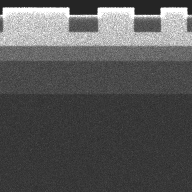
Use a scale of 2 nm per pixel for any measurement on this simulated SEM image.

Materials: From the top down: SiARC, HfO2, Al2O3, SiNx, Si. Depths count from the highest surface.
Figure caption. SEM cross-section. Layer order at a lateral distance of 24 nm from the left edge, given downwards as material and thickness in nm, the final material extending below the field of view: HfO2 76, Al2O3 30, SiNx 66, Si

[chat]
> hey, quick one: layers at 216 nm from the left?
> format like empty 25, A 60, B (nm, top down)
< HfO2 76, Al2O3 30, SiNx 66, Si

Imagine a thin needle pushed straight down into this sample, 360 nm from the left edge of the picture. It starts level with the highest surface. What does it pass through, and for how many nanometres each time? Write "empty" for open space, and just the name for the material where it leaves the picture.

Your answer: HfO2 76, Al2O3 30, SiNx 66, Si